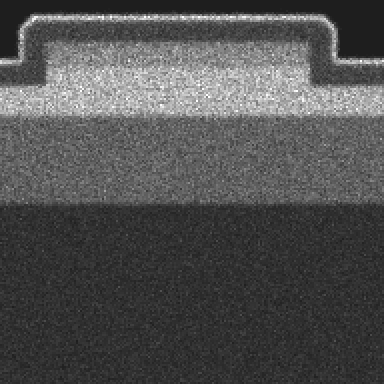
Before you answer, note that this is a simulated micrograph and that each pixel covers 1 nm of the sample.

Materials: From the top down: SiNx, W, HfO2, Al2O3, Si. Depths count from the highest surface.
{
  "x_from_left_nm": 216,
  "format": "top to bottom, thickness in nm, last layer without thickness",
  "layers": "SiNx 26, W 26, HfO2 48, Al2O3 88, Si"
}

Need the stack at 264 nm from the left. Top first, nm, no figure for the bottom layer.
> SiNx 26, W 26, HfO2 48, Al2O3 88, Si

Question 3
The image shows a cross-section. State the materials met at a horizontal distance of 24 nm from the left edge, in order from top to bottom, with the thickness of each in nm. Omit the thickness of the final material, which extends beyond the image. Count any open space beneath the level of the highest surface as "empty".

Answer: empty 8, SiNx 62, HfO2 30, Al2O3 88, Si